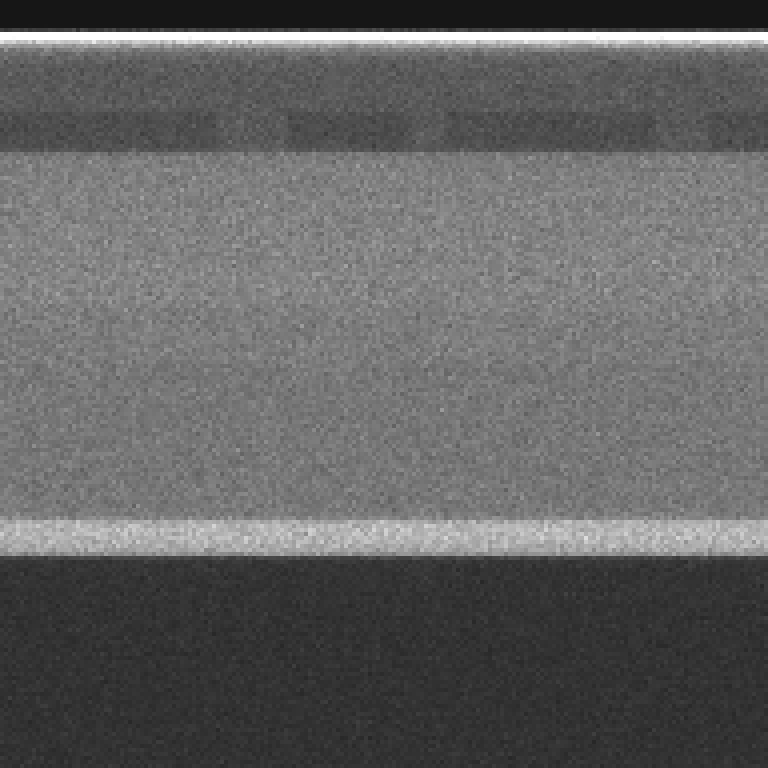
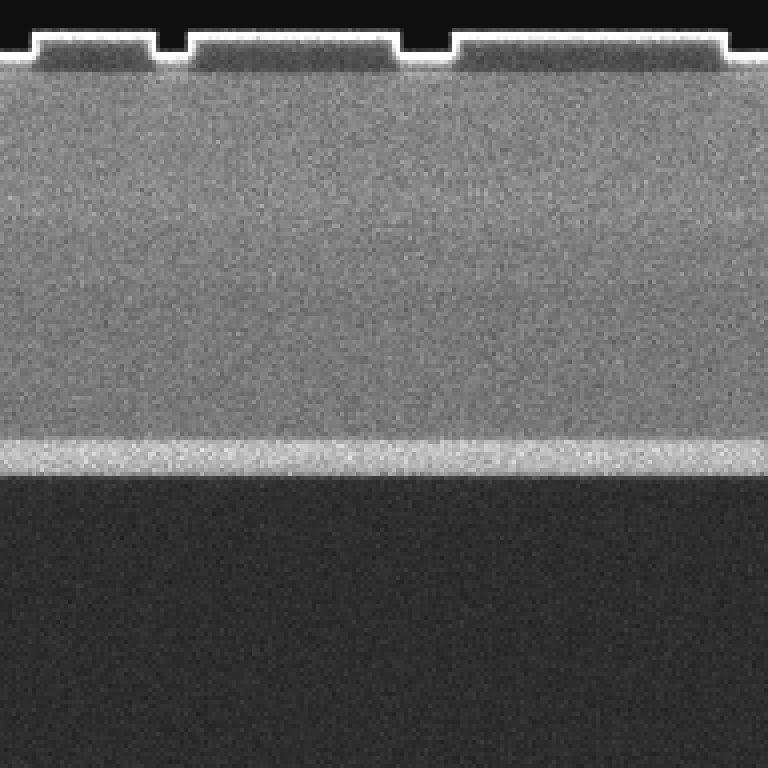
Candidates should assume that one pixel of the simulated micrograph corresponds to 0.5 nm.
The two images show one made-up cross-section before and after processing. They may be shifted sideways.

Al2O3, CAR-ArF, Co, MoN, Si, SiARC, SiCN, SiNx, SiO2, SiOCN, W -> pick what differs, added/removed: SiARC removed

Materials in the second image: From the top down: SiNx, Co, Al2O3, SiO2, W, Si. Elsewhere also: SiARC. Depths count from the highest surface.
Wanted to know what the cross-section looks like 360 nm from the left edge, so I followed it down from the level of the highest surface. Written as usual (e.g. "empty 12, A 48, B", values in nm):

SiNx 20, Co 78, Al2O3 28, SiO2 78, W 18, Si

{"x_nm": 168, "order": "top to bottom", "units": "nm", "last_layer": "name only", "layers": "SiNx 20, Co 78, Al2O3 28, SiO2 78, W 18, Si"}